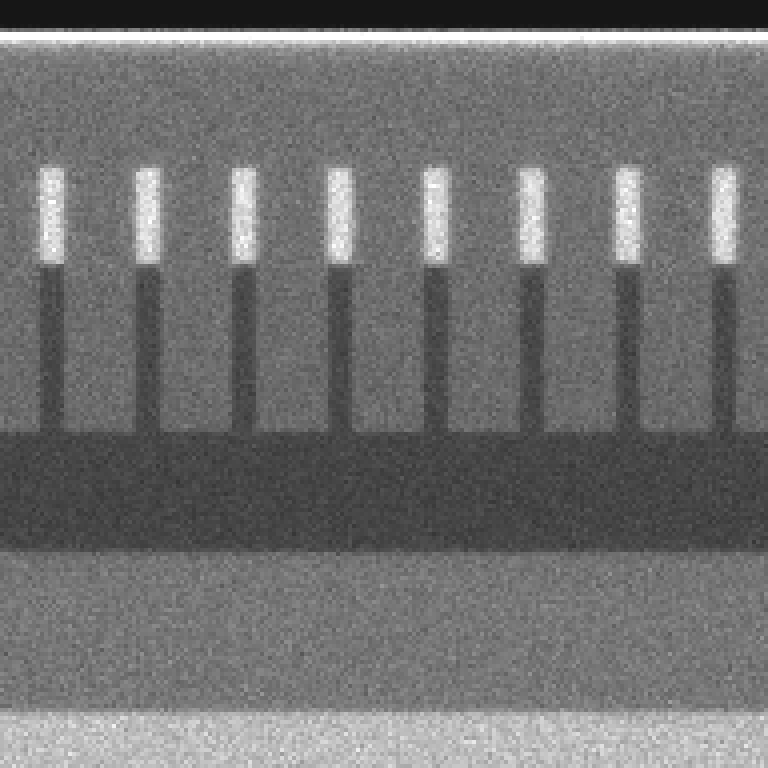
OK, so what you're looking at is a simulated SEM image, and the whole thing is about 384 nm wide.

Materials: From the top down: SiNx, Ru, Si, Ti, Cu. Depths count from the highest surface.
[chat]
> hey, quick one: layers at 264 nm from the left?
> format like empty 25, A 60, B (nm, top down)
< SiNx 68, Ru 48, Si 144, Ti 80, Cu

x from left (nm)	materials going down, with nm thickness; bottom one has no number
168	SiNx 68, Ru 48, Si 144, Ti 80, Cu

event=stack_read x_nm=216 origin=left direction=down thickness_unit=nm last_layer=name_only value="SiNx 68, Ru 48, Si 144, Ti 80, Cu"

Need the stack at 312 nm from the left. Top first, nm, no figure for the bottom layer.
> SiNx 68, Ru 48, Si 144, Ti 80, Cu